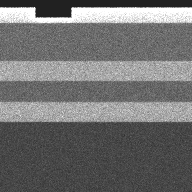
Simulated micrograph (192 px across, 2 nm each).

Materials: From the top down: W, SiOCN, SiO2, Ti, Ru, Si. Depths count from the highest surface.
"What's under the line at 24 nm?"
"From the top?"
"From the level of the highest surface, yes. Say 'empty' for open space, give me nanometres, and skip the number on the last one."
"W 30, SiOCN 76, SiO2 40, Ti 42, Ru 40, Si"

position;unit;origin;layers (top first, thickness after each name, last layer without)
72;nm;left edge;empty 20, W 10, SiOCN 76, SiO2 40, Ti 42, Ru 40, Si